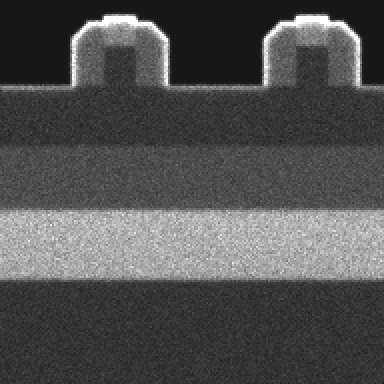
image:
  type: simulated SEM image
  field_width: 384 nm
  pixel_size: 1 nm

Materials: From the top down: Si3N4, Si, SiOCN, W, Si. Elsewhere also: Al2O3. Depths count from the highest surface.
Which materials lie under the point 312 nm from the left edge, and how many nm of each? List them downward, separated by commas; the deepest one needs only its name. Al2O3 30, Si 100, SiOCN 64, W 70, Si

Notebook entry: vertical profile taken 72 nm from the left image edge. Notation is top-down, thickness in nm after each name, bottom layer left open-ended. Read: empty 22, Si3N4 48, Si 60, SiOCN 64, W 70, Si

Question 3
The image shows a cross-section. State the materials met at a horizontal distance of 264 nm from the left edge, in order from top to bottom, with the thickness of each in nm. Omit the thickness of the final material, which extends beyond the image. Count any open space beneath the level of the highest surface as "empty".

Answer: empty 22, Si3N4 48, Si 60, SiOCN 64, W 70, Si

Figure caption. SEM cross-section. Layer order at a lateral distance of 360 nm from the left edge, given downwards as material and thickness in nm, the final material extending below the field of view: empty 70, Si 60, SiOCN 64, W 70, Si